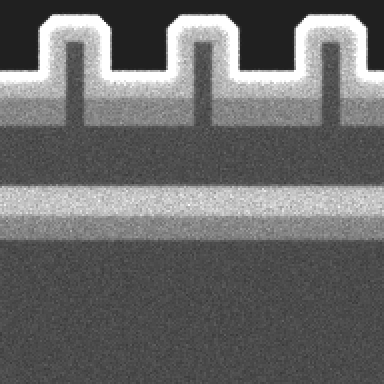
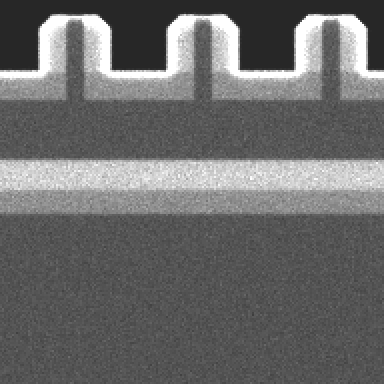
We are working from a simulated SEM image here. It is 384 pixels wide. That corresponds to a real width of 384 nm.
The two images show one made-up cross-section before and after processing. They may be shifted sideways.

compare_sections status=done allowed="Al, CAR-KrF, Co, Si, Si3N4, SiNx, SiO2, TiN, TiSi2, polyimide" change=removed material="SiO2"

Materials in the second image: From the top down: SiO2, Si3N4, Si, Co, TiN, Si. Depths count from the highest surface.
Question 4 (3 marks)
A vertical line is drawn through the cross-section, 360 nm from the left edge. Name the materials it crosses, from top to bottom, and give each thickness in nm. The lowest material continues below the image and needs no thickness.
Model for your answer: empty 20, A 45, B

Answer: empty 8, SiO2 48, Si3N4 28, Si 60, Co 30, TiN 24, Si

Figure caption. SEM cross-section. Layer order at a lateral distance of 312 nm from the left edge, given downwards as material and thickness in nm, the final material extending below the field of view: SiO2 56, Si3N4 28, Si 60, Co 30, TiN 24, Si